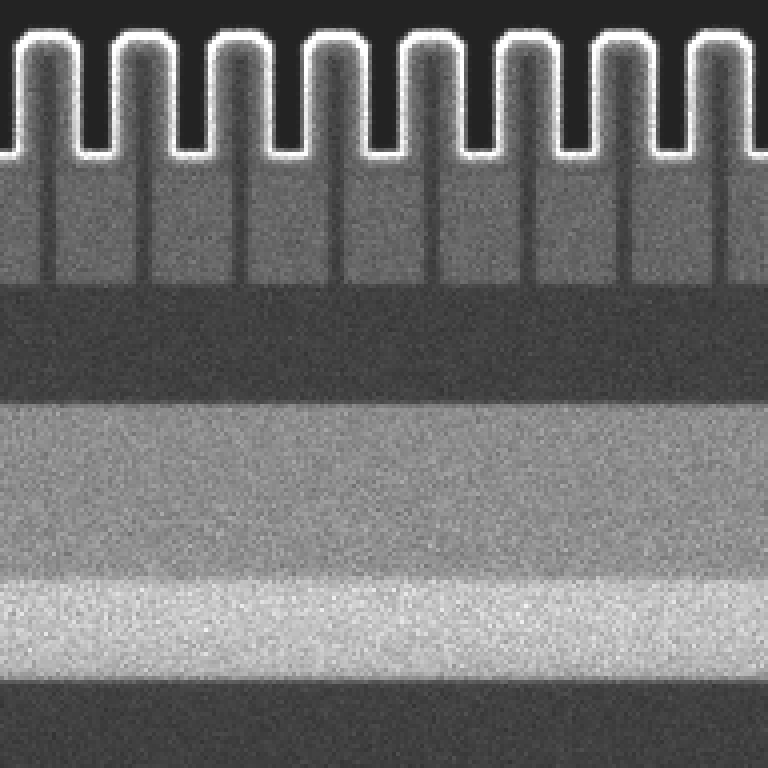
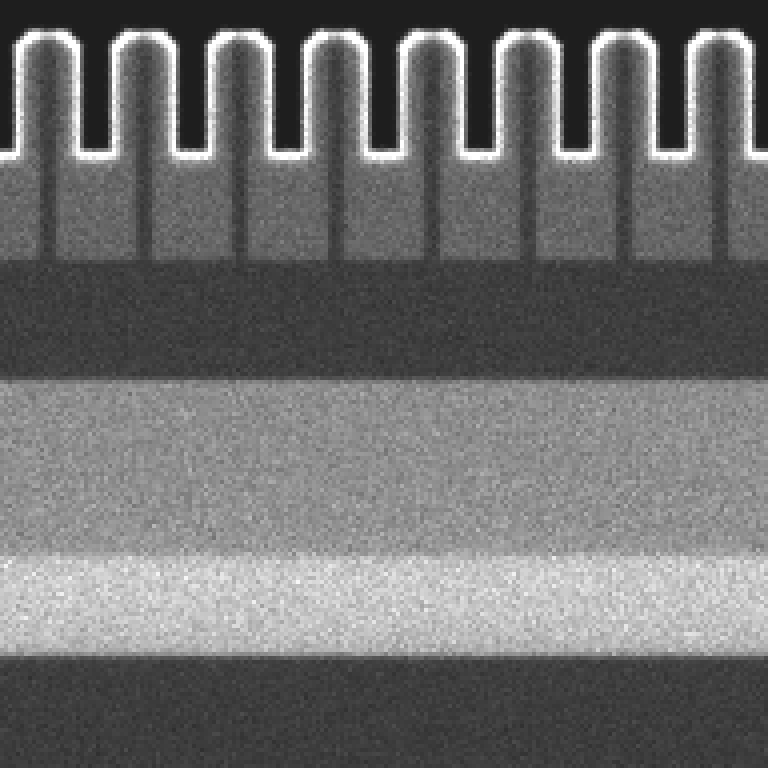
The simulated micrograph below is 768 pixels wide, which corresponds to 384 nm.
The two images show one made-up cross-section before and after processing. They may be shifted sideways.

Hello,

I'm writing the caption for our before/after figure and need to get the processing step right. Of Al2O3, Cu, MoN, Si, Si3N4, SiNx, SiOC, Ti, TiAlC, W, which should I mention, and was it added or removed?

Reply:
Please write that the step removed SiNx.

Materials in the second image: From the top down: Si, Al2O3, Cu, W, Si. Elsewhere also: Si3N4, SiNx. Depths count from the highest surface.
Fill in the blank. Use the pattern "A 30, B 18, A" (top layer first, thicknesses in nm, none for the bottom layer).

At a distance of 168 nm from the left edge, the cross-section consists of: Si 174, Al2O3 52, Cu 36, W 50, Si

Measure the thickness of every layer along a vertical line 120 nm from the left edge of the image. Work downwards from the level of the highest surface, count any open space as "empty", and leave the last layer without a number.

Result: Si 174, Al2O3 52, Cu 36, W 50, Si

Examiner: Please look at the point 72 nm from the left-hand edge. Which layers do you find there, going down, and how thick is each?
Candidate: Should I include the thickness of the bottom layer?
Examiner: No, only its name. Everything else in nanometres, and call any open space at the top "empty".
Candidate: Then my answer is Si 174, Al2O3 52, Cu 36, W 50, Si